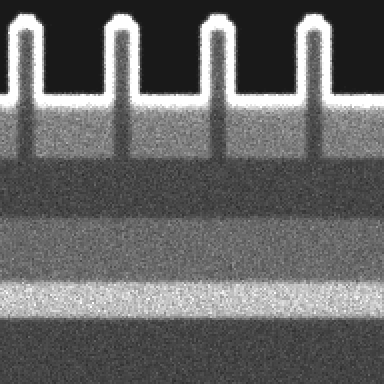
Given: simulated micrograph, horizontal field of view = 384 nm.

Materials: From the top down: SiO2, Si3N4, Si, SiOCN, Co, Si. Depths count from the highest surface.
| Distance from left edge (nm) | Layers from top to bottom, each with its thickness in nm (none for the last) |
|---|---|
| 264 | empty 80, SiO2 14, Si3N4 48, Si 60, SiOCN 64, Co 36, Si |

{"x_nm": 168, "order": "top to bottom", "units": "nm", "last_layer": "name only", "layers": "empty 80, SiO2 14, Si3N4 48, Si 60, SiOCN 64, Co 36, Si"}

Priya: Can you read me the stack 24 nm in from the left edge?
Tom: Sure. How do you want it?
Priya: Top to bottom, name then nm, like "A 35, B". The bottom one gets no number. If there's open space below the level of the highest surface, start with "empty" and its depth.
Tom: SiO2 14, Si 188, SiOCN 64, Co 36, Si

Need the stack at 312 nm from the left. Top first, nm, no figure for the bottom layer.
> SiO2 14, Si 188, SiOCN 64, Co 36, Si